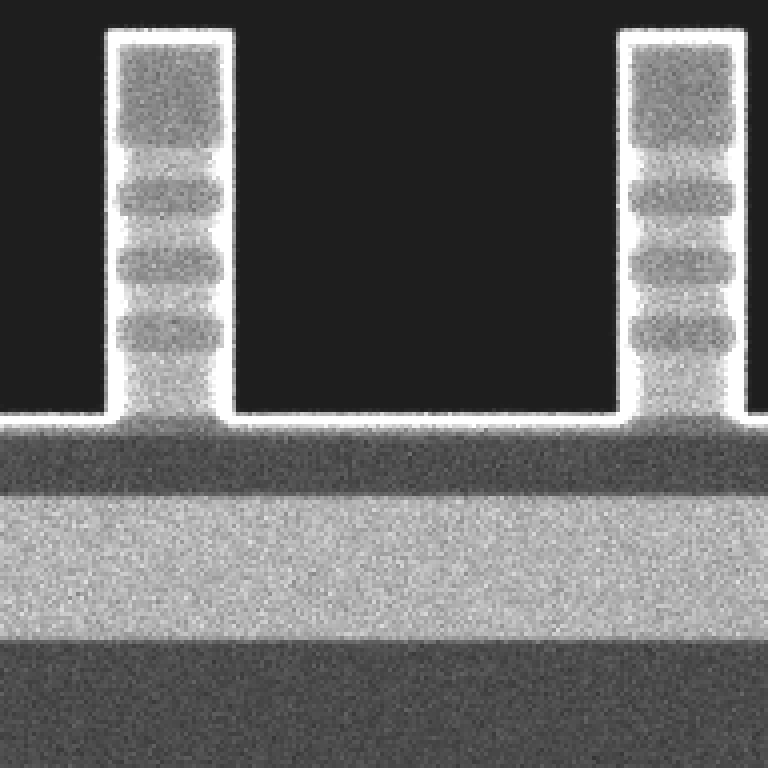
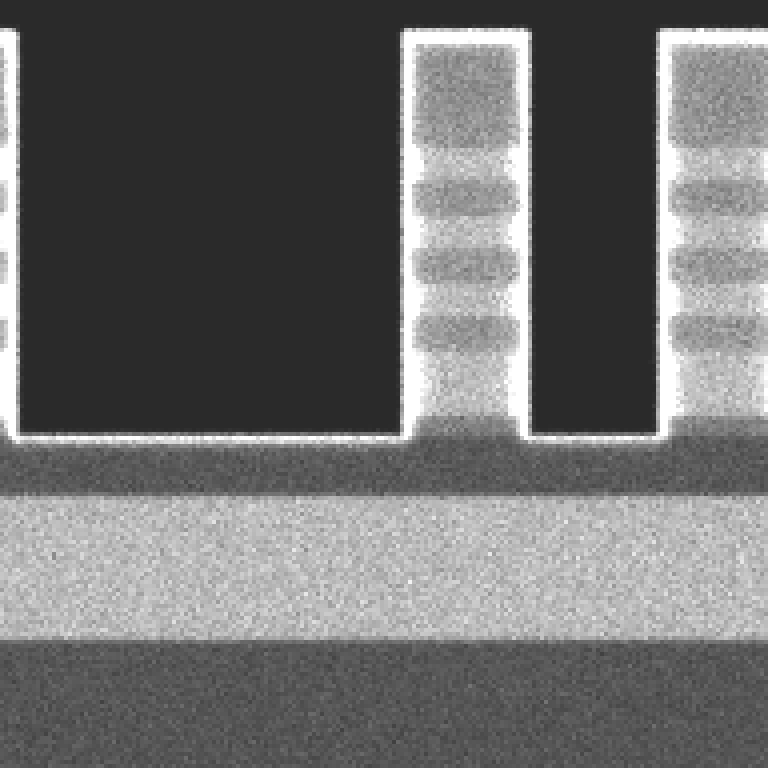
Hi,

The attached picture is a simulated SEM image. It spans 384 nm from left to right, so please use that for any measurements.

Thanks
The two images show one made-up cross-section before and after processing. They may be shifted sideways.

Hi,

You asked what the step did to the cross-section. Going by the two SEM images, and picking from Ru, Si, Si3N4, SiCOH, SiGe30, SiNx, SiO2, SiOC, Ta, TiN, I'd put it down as SiNx, removed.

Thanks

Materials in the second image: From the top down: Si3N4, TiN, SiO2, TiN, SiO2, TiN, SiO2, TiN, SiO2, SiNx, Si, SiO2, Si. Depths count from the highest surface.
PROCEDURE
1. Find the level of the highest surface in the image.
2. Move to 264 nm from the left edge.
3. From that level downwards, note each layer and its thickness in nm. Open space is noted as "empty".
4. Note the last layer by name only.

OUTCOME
empty 202, Si 30, SiO2 72, Si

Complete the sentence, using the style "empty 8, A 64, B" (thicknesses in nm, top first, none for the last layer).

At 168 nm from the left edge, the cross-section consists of empty 202, Si 30, SiO2 72, Si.